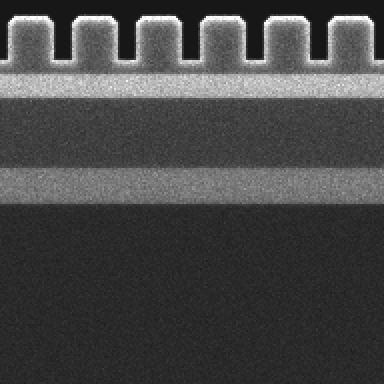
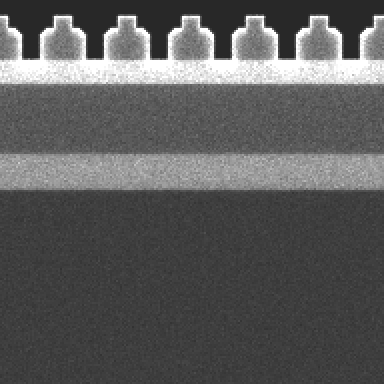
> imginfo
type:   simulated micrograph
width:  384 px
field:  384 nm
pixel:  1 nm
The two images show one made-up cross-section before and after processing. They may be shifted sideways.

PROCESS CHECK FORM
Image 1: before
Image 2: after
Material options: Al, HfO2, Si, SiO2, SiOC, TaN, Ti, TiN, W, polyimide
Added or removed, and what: removed, SiO2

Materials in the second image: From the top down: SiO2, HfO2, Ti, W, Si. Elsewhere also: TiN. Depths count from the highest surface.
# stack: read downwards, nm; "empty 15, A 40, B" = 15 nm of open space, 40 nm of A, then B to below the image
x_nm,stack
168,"empty 18, SiO2 26, HfO2 24, Ti 70, W 36, Si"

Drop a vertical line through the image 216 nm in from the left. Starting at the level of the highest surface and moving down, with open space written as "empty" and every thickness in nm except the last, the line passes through empty 44, HfO2 24, Ti 70, W 36, Si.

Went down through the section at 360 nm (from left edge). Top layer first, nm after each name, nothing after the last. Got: empty 18, SiO2 26, HfO2 24, Ti 70, W 36, Si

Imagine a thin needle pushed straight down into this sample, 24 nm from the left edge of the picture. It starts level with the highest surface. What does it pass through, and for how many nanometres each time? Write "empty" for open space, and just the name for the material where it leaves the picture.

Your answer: empty 44, HfO2 24, Ti 70, W 36, Si